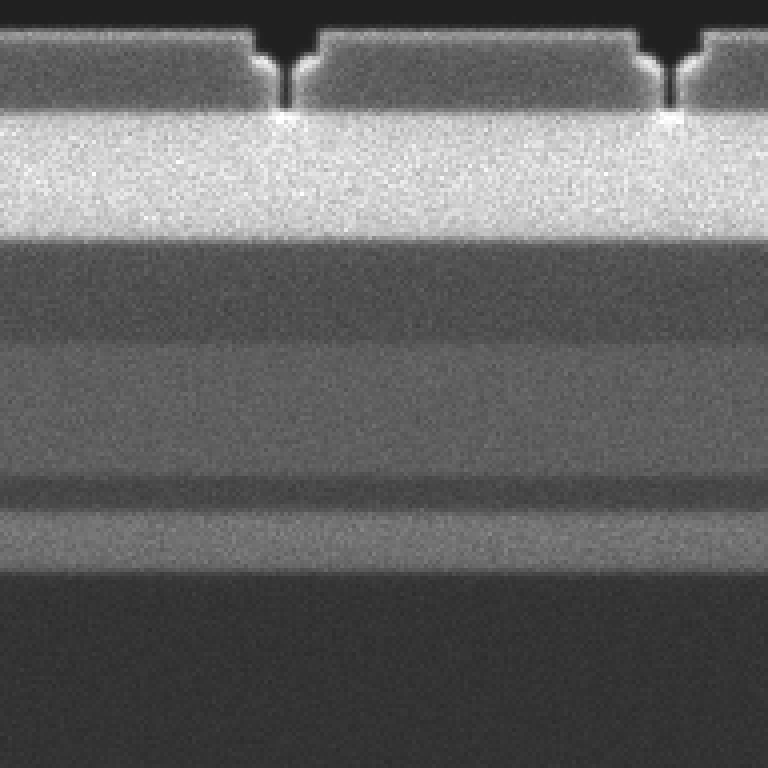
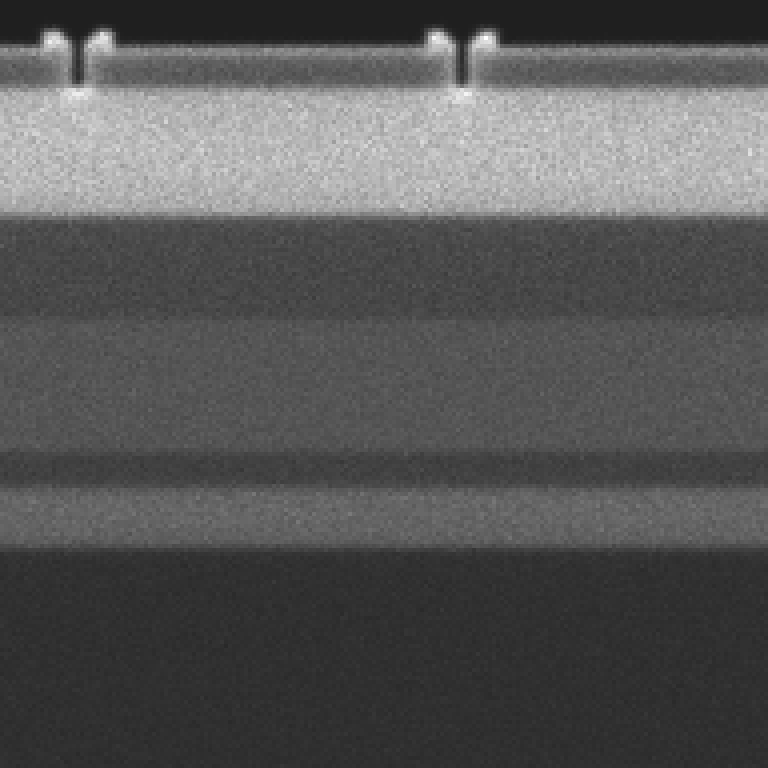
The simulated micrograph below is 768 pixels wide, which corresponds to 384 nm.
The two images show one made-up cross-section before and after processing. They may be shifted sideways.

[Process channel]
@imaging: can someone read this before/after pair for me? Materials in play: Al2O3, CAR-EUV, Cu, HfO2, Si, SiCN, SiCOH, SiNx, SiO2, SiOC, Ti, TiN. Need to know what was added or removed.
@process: TiN removed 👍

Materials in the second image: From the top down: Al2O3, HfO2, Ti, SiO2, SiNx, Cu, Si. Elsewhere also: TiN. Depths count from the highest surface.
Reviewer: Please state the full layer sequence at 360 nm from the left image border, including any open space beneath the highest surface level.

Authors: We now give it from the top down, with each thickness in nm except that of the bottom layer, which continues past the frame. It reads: empty 8, TiN 20, HfO2 64, Ti 52, SiO2 66, SiNx 18, Cu 30, Si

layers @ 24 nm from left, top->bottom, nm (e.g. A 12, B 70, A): Al2O3 28, HfO2 64, Ti 52, SiO2 66, SiNx 18, Cu 30, Si